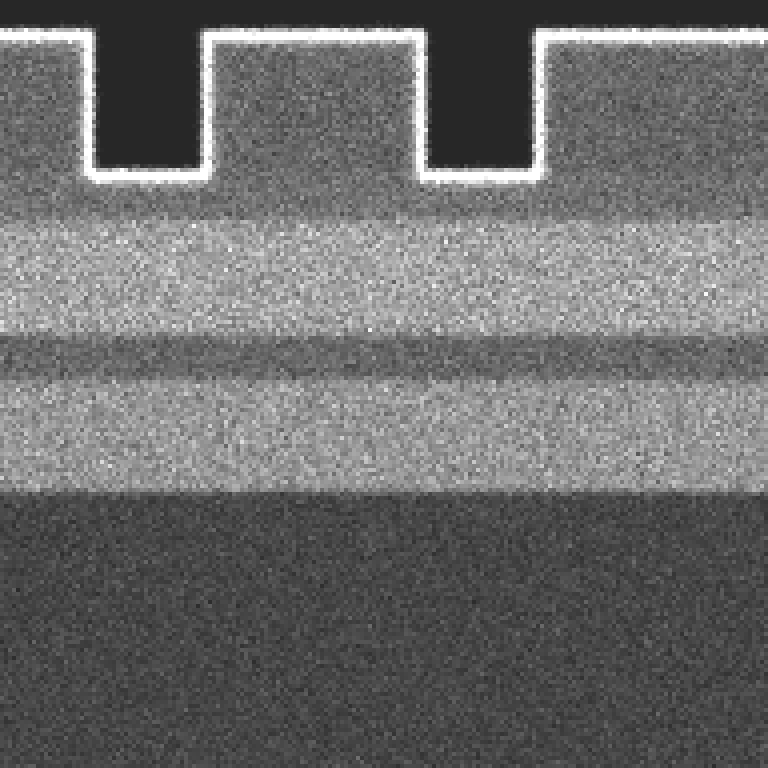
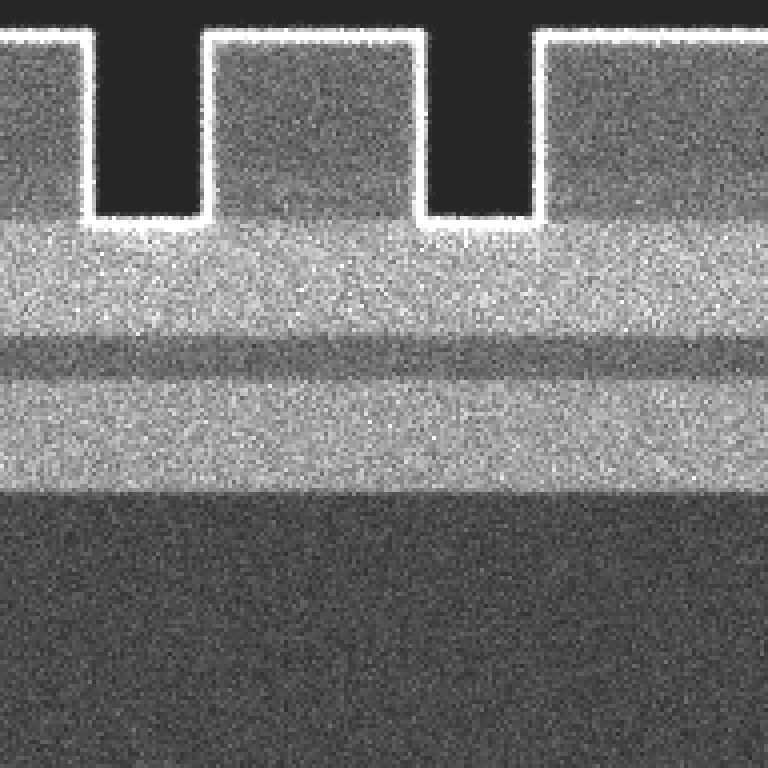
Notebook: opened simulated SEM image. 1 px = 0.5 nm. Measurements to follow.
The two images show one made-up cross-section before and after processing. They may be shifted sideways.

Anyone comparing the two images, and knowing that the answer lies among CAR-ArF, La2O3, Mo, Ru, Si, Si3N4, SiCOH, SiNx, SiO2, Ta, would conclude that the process removed Si3N4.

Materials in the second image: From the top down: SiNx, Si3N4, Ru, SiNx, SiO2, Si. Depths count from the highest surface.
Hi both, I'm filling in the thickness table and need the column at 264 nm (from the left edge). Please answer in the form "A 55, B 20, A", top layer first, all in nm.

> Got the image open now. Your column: empty 94, Ru 58, SiNx 22, SiO2 56, Si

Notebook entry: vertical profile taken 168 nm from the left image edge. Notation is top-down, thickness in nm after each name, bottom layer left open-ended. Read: SiNx 70, Si3N4 24, Ru 58, SiNx 22, SiO2 56, Si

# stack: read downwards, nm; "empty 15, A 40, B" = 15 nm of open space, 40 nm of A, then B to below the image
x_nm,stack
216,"empty 94, Ru 58, SiNx 22, SiO2 56, Si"